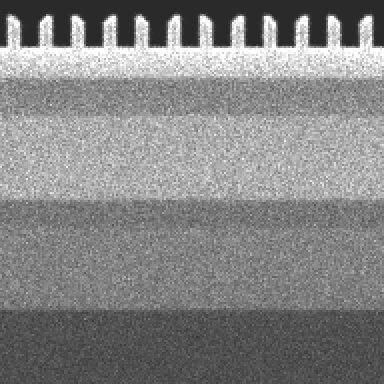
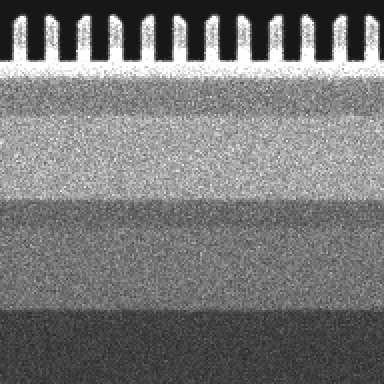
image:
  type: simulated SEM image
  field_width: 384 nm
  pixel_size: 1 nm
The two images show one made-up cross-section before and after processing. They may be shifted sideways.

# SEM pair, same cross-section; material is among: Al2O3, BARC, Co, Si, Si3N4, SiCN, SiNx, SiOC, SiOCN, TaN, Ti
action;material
removed;Co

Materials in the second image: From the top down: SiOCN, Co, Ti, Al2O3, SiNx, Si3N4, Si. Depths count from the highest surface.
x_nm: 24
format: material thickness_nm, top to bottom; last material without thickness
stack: SiOCN 32, Co 30, Ti 38, Al2O3 84, SiNx 28, Si3N4 82, Si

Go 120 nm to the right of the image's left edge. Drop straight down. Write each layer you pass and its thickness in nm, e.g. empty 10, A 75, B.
empty 6, SiOCN 26, Co 30, Ti 38, Al2O3 84, SiNx 28, Si3N4 82, Si